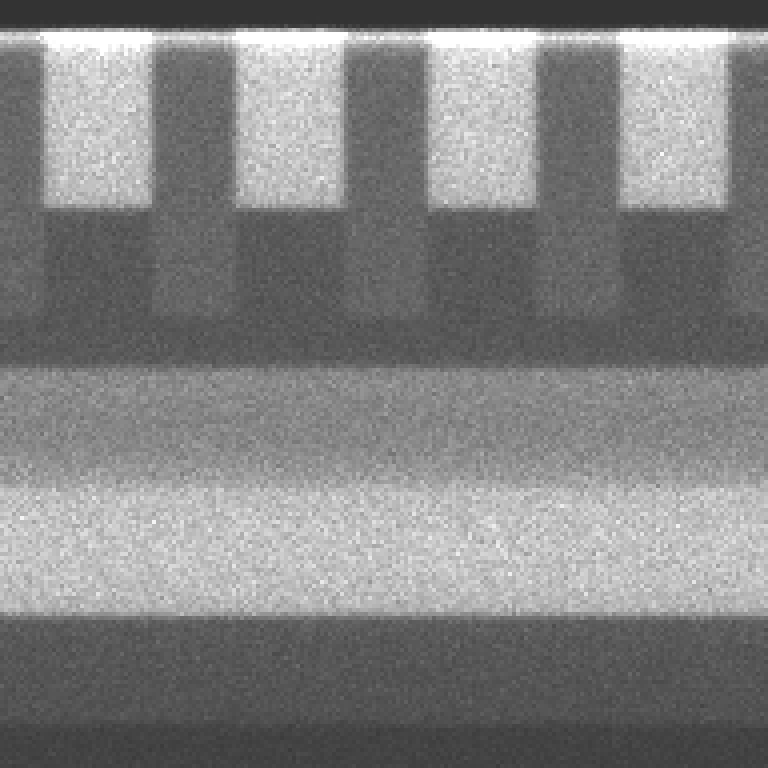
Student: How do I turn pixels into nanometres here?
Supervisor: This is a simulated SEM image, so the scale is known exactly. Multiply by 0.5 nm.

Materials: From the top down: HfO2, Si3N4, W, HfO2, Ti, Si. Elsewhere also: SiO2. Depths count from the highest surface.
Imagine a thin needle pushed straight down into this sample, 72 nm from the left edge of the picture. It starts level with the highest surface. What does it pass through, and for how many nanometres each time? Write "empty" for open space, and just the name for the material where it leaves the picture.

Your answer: HfO2 88, Si3N4 80, W 60, HfO2 64, Ti 54, Si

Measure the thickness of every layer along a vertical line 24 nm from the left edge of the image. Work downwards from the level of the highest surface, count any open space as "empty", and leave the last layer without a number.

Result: HfO2 88, Si3N4 80, W 60, HfO2 64, Ti 54, Si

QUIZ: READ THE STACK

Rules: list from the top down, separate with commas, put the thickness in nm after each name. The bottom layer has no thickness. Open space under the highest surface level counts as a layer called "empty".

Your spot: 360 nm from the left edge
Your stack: HfO2 88, Si3N4 80, W 60, HfO2 64, Ti 54, Si